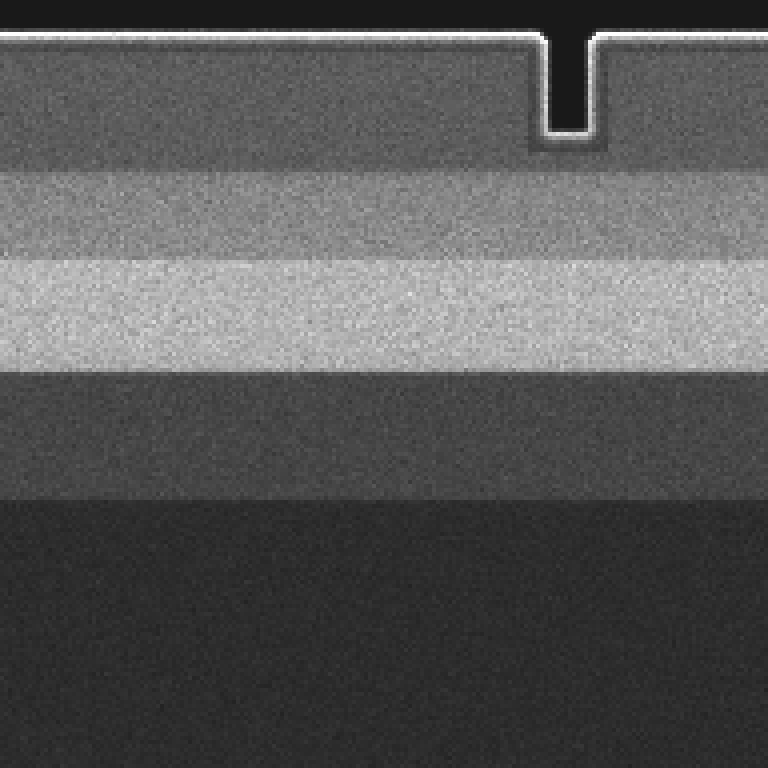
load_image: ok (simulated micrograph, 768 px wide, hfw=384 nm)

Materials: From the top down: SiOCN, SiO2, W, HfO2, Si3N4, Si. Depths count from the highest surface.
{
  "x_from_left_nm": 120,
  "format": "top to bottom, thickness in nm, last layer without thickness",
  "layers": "SiOCN 10, SiO2 60, W 44, HfO2 56, Si3N4 64, Si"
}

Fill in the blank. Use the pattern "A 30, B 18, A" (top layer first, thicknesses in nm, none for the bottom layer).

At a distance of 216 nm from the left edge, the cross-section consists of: SiOCN 10, SiO2 60, W 44, HfO2 56, Si3N4 64, Si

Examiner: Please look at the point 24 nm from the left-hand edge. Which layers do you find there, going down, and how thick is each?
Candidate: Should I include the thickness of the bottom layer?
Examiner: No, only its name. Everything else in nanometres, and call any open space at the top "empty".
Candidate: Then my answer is SiOCN 10, SiO2 60, W 44, HfO2 56, Si3N4 64, Si